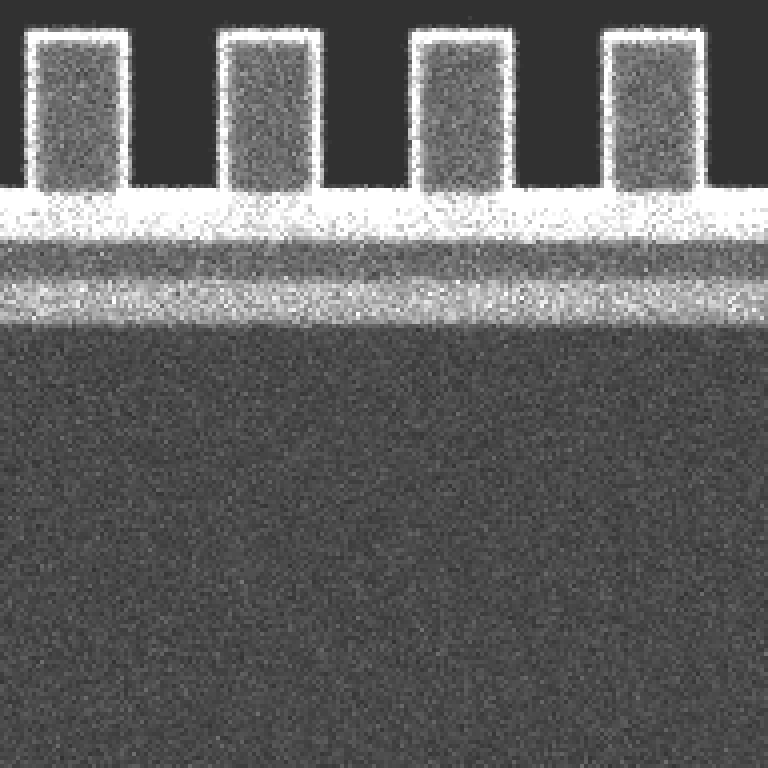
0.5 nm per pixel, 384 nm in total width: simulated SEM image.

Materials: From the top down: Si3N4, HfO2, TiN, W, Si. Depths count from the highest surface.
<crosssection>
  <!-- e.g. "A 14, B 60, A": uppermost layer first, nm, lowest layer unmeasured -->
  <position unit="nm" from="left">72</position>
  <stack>empty 80, HfO2 24, TiN 20, W 22, Si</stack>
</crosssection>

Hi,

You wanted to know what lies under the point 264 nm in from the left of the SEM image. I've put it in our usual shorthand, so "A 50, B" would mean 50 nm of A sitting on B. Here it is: empty 80, HfO2 24, TiN 20, W 22, Si